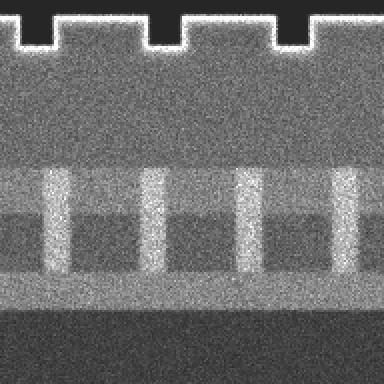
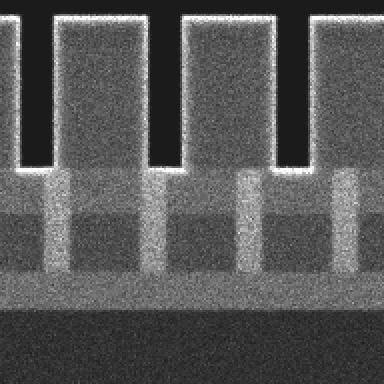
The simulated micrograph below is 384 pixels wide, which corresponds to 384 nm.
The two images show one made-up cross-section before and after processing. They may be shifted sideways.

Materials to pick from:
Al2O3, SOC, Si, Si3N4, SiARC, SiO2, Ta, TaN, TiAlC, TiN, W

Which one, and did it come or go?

SOC - removed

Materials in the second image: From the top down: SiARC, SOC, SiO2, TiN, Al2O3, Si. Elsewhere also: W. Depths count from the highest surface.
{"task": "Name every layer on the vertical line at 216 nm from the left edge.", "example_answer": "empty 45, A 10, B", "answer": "SiARC 30, SOC 122, SiO2 46, TiN 58, Al2O3 38, Si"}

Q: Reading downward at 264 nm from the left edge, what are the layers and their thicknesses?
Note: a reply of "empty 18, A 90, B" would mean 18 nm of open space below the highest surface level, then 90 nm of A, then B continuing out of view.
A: SiARC 30, SOC 122, SiO2 46, TiN 58, Al2O3 38, Si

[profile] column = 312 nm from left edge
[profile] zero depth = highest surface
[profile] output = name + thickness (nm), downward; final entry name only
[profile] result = SiARC 30, SOC 122, SiO2 46, TiN 58, Al2O3 38, Si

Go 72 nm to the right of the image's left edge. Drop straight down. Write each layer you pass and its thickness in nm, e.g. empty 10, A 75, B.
SiARC 30, SOC 122, SiO2 46, TiN 58, Al2O3 38, Si